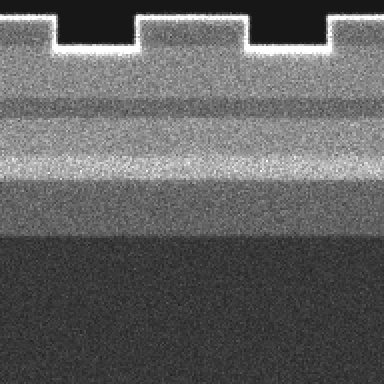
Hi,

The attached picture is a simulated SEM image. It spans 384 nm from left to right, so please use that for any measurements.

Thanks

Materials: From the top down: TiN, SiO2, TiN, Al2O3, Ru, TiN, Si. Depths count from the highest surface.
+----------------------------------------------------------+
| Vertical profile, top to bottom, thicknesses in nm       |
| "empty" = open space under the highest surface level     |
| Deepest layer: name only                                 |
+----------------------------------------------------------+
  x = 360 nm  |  TiN 30, SiO2 52, TiN 20, Al2O3 38, Ru 24, TiN 56, Si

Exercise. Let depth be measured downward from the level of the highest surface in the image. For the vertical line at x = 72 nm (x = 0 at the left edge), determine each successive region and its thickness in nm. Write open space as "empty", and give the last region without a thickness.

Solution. empty 30, SiO2 52, TiN 20, Al2O3 38, Ru 24, TiN 56, Si